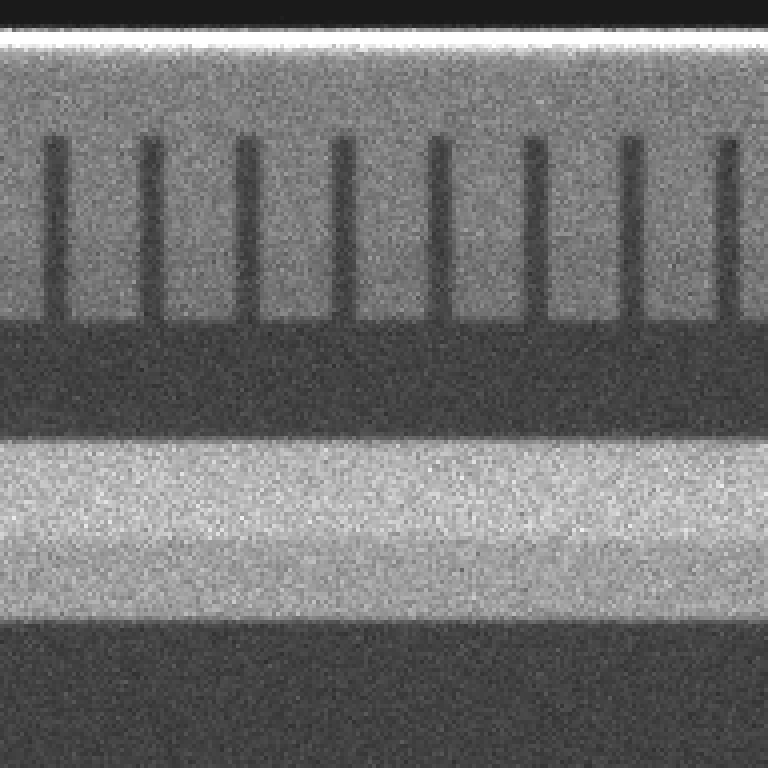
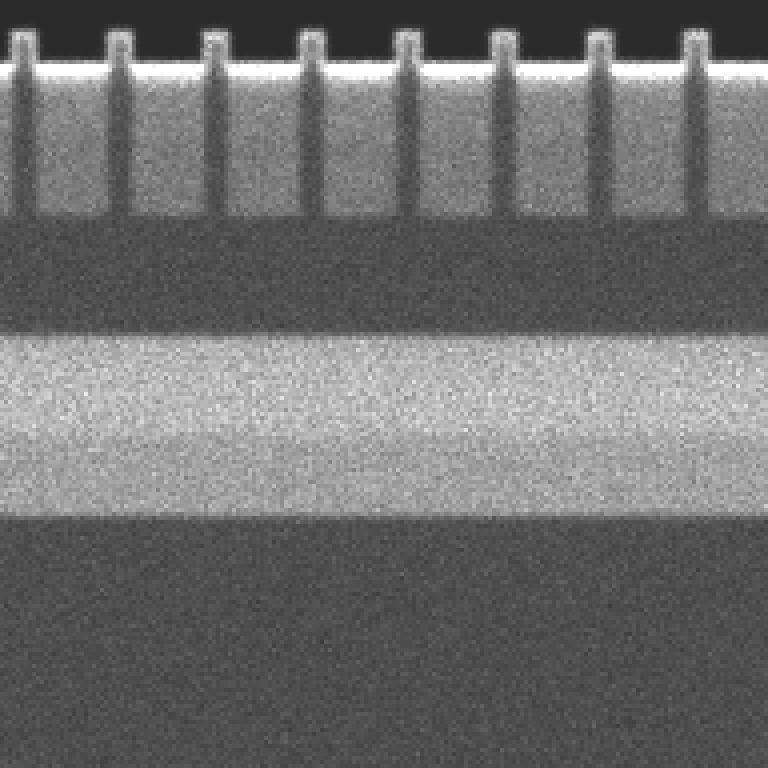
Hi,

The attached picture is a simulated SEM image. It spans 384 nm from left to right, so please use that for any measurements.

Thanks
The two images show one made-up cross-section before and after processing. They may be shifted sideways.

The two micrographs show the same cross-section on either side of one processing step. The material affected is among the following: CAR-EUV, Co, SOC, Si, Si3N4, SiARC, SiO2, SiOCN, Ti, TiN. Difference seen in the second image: SOC removed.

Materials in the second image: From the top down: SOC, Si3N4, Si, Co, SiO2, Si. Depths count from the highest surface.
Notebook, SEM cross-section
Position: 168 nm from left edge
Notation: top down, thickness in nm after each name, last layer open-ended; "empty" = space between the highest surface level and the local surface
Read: empty 16, SOC 36, Si3N4 40, Si 60, Co 50, SiO2 40, Si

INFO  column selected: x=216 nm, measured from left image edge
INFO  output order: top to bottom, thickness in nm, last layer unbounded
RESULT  empty 16, SOC 36, Si3N4 40, Si 60, Co 50, SiO2 40, Si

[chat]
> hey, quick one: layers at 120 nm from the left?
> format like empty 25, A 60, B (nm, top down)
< empty 16, SOC 36, Si3N4 40, Si 60, Co 50, SiO2 40, Si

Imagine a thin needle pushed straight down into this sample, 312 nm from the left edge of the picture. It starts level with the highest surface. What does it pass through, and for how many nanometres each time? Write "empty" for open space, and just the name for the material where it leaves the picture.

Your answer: empty 16, SOC 36, Si3N4 40, Si 60, Co 50, SiO2 40, Si